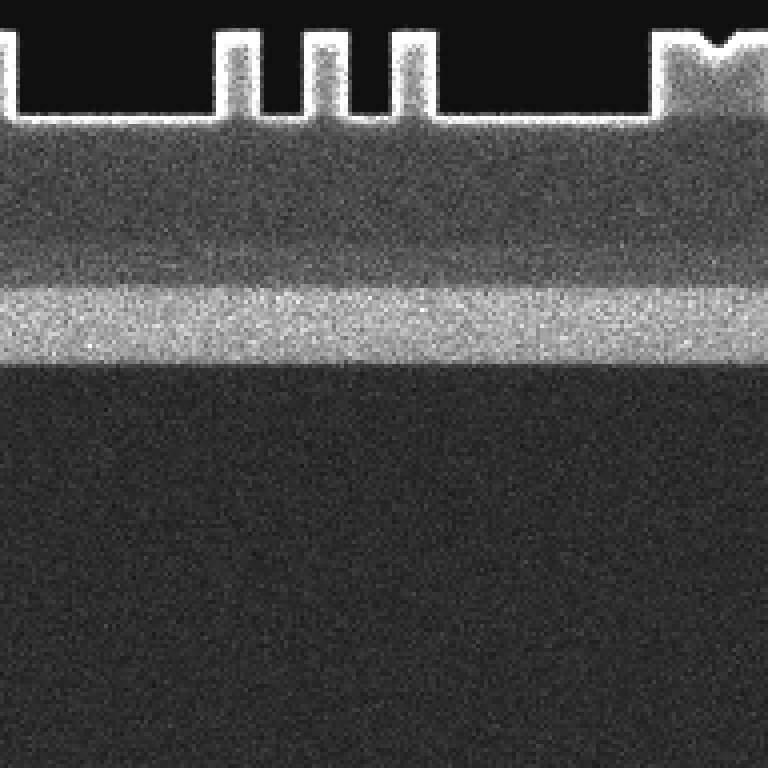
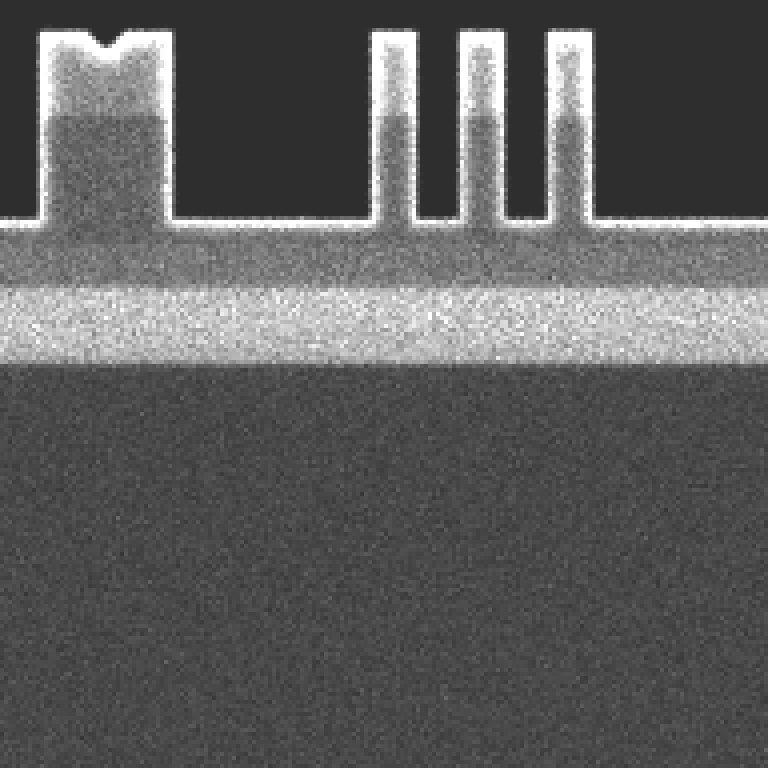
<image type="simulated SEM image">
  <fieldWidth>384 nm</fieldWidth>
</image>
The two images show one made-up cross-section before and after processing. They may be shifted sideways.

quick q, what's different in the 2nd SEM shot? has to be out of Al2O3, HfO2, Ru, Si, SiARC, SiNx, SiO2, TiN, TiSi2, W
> SiNx removed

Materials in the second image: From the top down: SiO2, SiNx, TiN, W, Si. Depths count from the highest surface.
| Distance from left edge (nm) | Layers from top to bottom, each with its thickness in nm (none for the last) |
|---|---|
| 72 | SiO2 42, SiNx 64, TiN 22, W 38, Si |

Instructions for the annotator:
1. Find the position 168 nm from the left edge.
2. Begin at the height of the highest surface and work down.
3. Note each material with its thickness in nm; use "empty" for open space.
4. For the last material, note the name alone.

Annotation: empty 94, SiNx 12, TiN 22, W 38, Si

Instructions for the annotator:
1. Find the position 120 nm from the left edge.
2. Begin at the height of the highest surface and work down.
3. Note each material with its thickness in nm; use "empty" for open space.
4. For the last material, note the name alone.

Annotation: empty 94, SiNx 12, TiN 22, W 38, Si